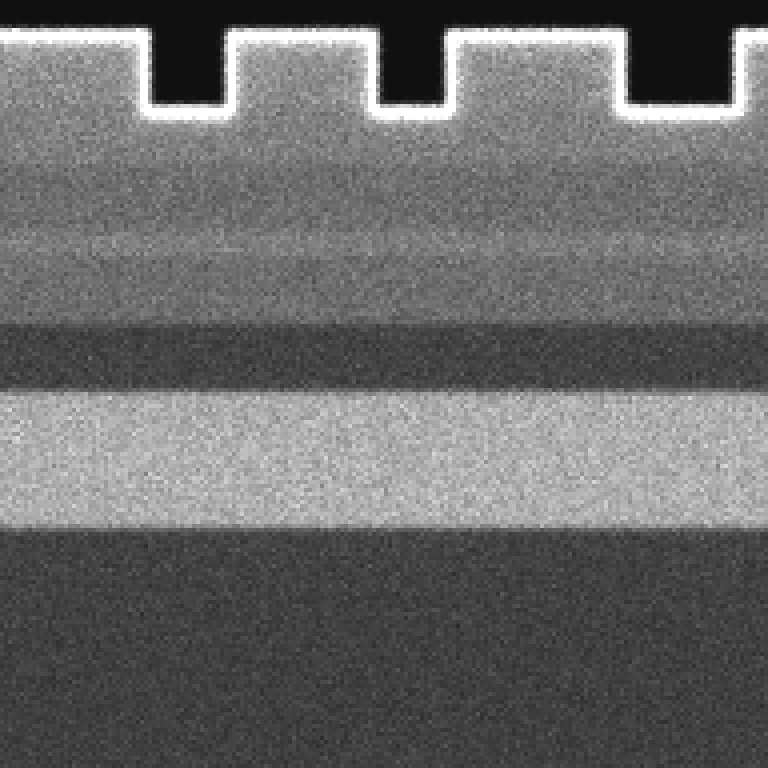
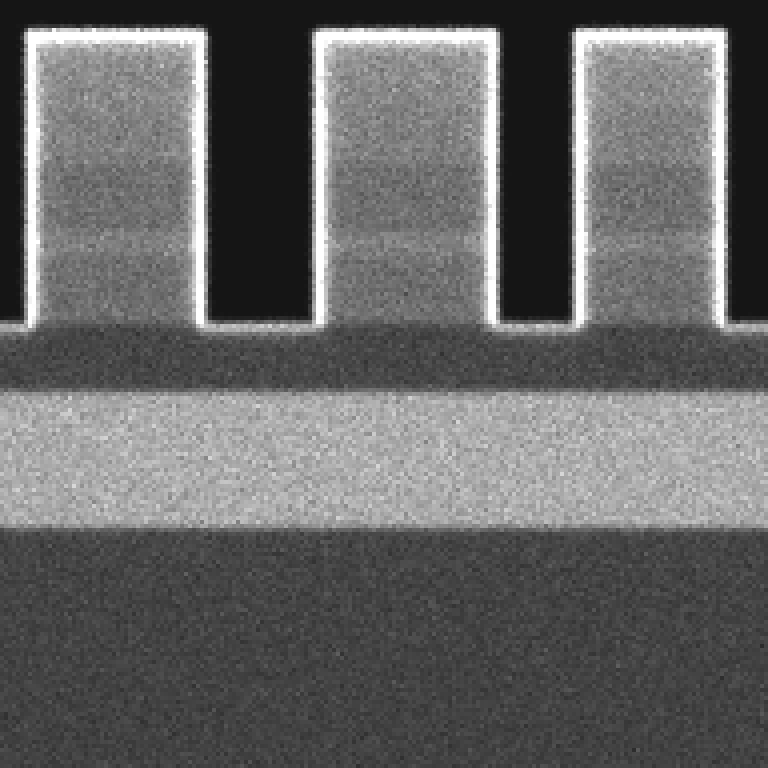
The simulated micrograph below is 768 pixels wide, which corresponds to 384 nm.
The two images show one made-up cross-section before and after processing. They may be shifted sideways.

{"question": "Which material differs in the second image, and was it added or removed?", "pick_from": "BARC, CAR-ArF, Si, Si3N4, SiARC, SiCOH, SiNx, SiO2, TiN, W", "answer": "Si3N4 and SiNx, removed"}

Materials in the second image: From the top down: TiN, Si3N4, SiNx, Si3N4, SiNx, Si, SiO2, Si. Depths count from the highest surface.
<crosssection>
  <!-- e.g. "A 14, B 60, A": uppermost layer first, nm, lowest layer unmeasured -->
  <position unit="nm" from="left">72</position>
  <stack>TiN 38, Si3N4 28, SiNx 34, Si3N4 12, SiNx 34, Si 34, SiO2 68, Si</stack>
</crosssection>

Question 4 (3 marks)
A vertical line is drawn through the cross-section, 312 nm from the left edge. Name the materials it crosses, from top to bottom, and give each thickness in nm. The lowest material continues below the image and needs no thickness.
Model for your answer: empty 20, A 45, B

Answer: TiN 38, Si3N4 28, SiNx 34, Si3N4 12, SiNx 34, Si 34, SiO2 68, Si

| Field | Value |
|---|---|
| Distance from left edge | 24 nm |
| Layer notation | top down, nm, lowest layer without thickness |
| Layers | TiN 38, Si3N4 28, SiNx 34, Si3N4 12, SiNx 34, Si 34, SiO2 68, Si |